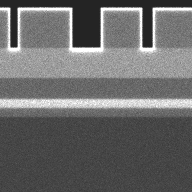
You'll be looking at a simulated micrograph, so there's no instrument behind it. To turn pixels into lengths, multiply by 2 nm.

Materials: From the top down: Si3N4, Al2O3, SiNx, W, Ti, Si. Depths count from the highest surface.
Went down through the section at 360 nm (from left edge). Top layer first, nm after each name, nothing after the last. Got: Si3N4 80, Al2O3 60, SiNx 42, W 18, Ti 18, Si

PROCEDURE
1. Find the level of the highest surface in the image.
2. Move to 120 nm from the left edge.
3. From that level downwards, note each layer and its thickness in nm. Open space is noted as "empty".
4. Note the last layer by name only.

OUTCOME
Si3N4 80, Al2O3 60, SiNx 42, W 18, Ti 18, Si